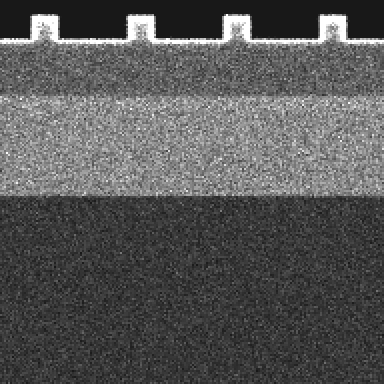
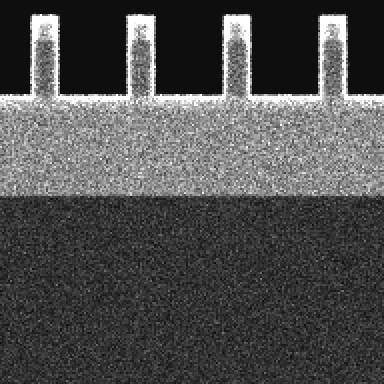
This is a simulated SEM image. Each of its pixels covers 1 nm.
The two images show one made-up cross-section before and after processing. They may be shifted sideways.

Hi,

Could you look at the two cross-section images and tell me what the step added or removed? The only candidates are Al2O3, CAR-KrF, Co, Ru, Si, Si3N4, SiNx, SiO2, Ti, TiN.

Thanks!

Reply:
removed TiN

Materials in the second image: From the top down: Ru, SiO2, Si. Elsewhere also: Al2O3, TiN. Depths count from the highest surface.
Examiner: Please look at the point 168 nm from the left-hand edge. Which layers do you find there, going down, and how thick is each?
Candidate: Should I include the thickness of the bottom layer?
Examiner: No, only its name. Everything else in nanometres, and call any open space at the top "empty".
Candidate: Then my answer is empty 80, Ru 14, SiO2 86, Si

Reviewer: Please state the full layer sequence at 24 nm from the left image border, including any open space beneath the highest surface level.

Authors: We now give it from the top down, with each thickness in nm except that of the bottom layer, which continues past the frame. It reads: empty 80, Ru 14, SiO2 86, Si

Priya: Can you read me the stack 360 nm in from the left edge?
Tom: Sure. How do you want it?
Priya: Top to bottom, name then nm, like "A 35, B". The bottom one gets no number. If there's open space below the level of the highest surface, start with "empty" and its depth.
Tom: empty 80, Ru 14, SiO2 86, Si